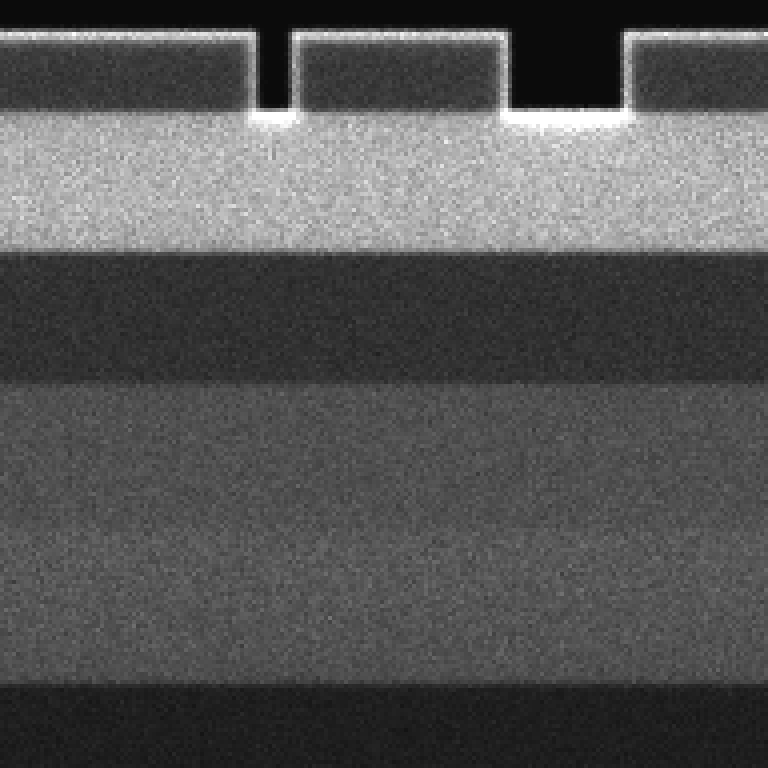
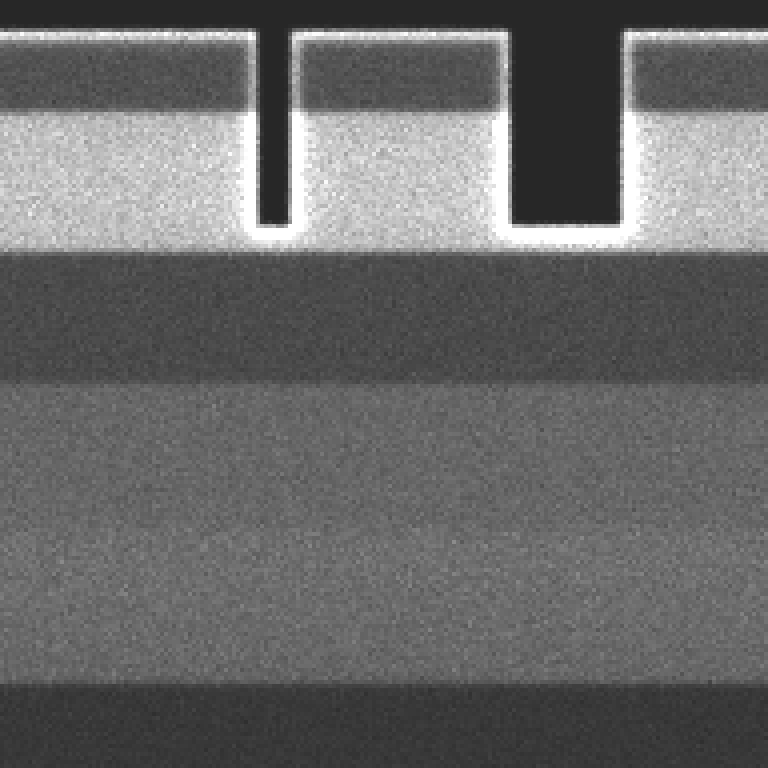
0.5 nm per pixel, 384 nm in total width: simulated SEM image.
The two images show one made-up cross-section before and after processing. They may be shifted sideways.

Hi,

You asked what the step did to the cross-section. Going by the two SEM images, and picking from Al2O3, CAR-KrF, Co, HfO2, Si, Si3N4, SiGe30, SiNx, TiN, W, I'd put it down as HfO2, removed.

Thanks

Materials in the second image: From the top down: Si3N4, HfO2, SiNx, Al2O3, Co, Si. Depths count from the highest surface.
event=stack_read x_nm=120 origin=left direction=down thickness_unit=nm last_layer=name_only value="Si3N4 40, HfO2 70, SiNx 66, Al2O3 72, Co 78, Si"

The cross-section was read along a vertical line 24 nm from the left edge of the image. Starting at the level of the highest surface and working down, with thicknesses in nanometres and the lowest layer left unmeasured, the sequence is Si3N4 40, HfO2 70, SiNx 66, Al2O3 72, Co 78, Si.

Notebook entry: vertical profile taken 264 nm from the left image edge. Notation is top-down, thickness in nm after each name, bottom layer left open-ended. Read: empty 98, HfO2 12, SiNx 66, Al2O3 72, Co 78, Si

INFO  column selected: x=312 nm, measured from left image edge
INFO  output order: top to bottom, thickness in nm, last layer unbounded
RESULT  Si3N4 40, HfO2 70, SiNx 66, Al2O3 72, Co 78, Si